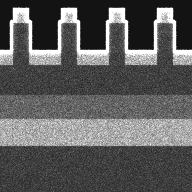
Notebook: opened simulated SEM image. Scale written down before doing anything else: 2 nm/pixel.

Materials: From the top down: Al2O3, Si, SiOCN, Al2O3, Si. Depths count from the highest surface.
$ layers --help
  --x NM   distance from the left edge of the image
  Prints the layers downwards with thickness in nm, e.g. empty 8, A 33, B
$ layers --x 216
empty 24, Al2O3 90, Si 60, SiOCN 48, Al2O3 54, Si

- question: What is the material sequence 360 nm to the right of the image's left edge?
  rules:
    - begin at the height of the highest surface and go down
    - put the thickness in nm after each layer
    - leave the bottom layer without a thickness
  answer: empty 84, Al2O3 30, Si 60, SiOCN 48, Al2O3 54, Si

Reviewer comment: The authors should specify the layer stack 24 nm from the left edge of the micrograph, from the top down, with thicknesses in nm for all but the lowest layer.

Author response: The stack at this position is empty 24, Al2O3 90, Si 60, SiOCN 48, Al2O3 54, Si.